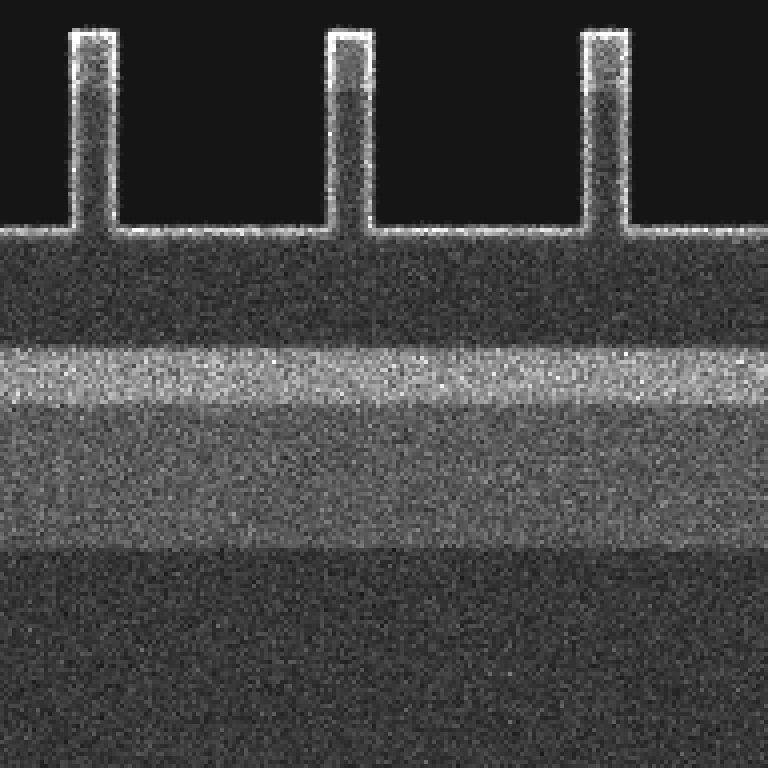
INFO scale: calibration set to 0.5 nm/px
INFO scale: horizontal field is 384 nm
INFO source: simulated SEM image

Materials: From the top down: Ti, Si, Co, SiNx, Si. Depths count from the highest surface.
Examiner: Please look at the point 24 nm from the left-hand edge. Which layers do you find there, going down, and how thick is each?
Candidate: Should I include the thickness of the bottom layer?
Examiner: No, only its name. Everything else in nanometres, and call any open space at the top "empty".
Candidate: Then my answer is empty 98, Si 60, Co 28, SiNx 72, Si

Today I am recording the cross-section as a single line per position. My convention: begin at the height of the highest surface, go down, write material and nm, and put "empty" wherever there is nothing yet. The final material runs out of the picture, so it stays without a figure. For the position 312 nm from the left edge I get Ti 30, Si 128, Co 28, SiNx 72, Si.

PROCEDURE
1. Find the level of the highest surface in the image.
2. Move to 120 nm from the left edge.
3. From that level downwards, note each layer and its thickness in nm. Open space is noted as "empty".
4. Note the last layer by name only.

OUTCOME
empty 98, Si 60, Co 28, SiNx 72, Si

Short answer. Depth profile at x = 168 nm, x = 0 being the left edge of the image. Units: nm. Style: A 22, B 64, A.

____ Ti 30, Si 128, Co 28, SiNx 72, Si